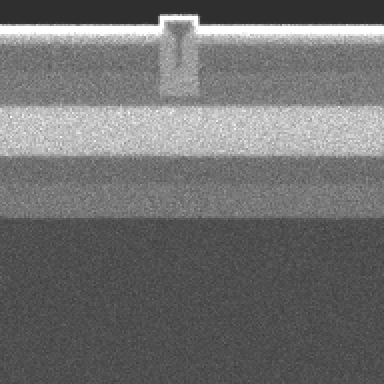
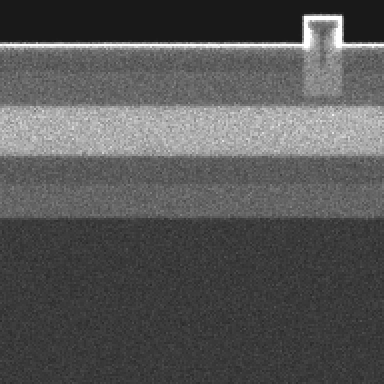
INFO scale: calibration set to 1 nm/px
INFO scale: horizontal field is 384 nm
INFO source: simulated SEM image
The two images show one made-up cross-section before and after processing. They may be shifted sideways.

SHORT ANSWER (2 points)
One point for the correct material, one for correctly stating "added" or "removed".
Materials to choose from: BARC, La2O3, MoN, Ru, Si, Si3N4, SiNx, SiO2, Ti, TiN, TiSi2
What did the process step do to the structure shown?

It removed SiO2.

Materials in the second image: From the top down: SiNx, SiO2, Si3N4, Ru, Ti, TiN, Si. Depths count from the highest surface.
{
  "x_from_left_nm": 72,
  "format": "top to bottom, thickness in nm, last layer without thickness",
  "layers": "empty 28, Ti 28, Si3N4 34, Ru 50, Ti 28, TiN 34, Si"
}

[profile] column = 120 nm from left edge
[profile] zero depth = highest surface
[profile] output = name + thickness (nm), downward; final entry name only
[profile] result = empty 28, Ti 28, Si3N4 34, Ru 50, Ti 28, TiN 34, Si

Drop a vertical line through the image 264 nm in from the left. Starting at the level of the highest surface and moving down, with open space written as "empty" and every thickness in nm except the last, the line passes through empty 28, Ti 28, Si3N4 34, Ru 50, Ti 28, TiN 34, Si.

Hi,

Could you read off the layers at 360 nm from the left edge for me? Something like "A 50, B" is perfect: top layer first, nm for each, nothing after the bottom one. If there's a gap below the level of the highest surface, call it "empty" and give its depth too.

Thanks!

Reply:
empty 28, Ti 28, Si3N4 34, Ru 50, Ti 28, TiN 34, Si